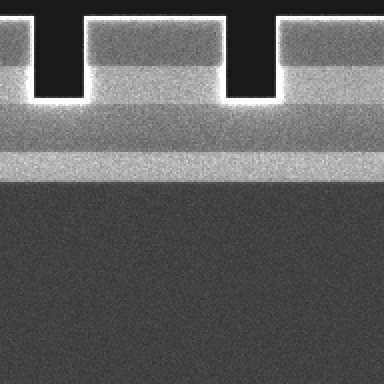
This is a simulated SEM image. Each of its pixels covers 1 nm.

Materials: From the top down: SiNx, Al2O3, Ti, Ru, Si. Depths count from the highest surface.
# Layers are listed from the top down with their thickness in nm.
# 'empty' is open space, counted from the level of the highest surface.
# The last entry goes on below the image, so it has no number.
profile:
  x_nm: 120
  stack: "SiNx 50, Al2O3 38, Ti 48, Ru 30, Si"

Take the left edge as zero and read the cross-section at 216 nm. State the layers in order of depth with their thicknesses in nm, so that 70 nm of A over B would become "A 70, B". SiNx 50, Al2O3 38, Ti 48, Ru 30, Si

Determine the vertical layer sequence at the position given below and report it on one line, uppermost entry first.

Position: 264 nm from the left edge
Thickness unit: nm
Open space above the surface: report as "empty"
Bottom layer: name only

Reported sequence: empty 82, Al2O3 6, Ti 48, Ru 30, Si